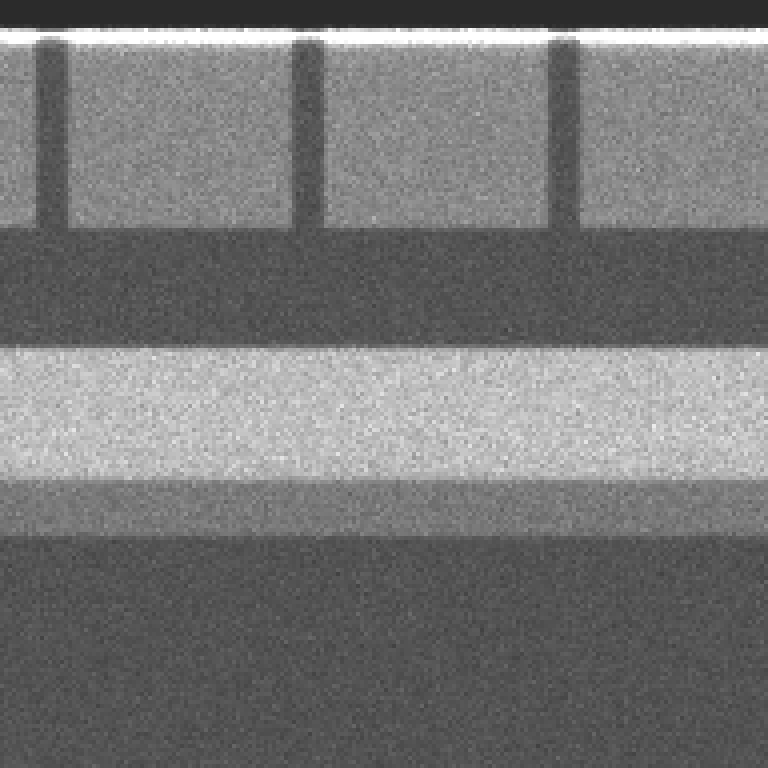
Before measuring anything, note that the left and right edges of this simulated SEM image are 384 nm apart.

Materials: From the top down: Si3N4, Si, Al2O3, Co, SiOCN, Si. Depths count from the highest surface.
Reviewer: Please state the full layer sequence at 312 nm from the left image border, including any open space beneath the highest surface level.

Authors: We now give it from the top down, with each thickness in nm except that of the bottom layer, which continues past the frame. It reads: Si3N4 98, Si 60, Al2O3 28, Co 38, SiOCN 28, Si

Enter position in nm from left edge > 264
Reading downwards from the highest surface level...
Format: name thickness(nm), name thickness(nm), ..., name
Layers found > Si3N4 98, Si 60, Al2O3 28, Co 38, SiOCN 28, Si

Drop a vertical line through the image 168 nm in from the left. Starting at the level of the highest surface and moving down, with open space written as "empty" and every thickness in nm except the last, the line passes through Si3N4 98, Si 60, Al2O3 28, Co 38, SiOCN 28, Si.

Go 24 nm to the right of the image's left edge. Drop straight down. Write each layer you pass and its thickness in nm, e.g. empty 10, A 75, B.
Si 158, Al2O3 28, Co 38, SiOCN 28, Si